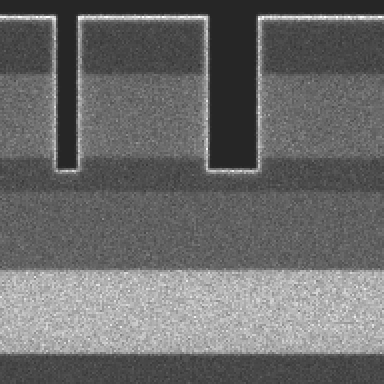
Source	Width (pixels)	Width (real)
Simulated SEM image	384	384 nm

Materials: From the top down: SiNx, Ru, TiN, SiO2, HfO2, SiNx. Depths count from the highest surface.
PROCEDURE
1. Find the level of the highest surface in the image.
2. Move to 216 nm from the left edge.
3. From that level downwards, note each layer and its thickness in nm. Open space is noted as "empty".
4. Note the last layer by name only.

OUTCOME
empty 154, TiN 22, SiO2 78, HfO2 84, SiNx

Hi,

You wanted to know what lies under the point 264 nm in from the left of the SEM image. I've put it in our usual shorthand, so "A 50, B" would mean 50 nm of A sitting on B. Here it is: SiNx 58, Ru 84, TiN 34, SiO2 78, HfO2 84, SiNx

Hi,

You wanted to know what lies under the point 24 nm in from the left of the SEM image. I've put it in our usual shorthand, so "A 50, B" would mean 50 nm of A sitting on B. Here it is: SiNx 58, Ru 84, TiN 34, SiO2 78, HfO2 84, SiNx